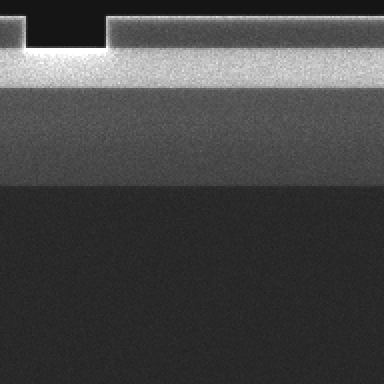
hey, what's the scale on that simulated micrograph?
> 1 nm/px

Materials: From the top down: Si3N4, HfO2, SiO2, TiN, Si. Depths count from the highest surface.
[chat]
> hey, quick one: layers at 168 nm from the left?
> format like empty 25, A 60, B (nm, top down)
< Si3N4 32, HfO2 40, SiO2 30, TiN 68, Si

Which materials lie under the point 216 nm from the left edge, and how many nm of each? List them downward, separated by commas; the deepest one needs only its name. Si3N4 32, HfO2 40, SiO2 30, TiN 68, Si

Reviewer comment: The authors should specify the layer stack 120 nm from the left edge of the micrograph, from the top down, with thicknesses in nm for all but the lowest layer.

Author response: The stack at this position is Si3N4 32, HfO2 40, SiO2 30, TiN 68, Si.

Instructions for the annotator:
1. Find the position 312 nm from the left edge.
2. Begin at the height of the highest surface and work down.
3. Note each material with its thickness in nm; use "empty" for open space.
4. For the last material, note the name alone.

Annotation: Si3N4 32, HfO2 40, SiO2 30, TiN 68, Si